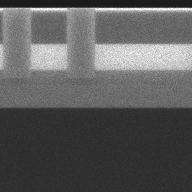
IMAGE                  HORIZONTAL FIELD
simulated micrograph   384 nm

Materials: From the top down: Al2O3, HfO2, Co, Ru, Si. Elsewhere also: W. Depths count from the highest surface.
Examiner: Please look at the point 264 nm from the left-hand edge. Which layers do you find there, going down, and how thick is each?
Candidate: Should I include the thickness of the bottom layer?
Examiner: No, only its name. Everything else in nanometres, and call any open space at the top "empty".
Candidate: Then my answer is Al2O3 72, HfO2 52, Co 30, Ru 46, Si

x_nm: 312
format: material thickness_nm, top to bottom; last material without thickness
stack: Al2O3 72, HfO2 52, Co 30, Ru 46, Si